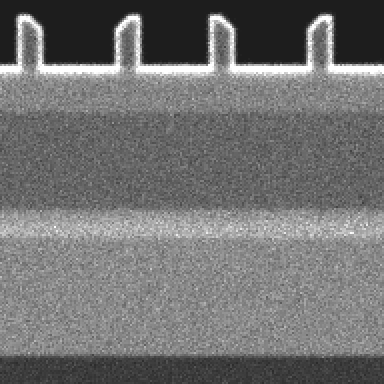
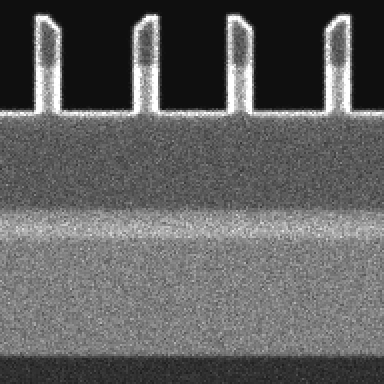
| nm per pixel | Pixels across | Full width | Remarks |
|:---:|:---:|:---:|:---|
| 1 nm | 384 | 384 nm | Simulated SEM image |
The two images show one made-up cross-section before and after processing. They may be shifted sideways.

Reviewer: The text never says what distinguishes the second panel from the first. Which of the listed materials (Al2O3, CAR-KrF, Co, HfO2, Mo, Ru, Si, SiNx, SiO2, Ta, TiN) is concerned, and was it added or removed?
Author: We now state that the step removed SiO2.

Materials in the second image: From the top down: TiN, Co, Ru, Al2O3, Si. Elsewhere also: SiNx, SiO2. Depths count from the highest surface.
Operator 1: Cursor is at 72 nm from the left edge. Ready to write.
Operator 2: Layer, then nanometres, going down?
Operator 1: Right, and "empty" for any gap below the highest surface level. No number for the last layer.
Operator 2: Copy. empty 96, TiN 98, Co 12, Ru 16, Al2O3 118, Si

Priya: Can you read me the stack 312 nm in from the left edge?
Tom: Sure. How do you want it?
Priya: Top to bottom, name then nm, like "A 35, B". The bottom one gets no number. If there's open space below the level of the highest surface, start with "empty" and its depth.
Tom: empty 96, TiN 98, Co 12, Ru 16, Al2O3 118, Si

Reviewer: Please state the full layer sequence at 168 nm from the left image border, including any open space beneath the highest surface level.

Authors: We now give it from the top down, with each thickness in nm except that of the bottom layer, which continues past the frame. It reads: empty 96, TiN 98, Co 12, Ru 16, Al2O3 118, Si